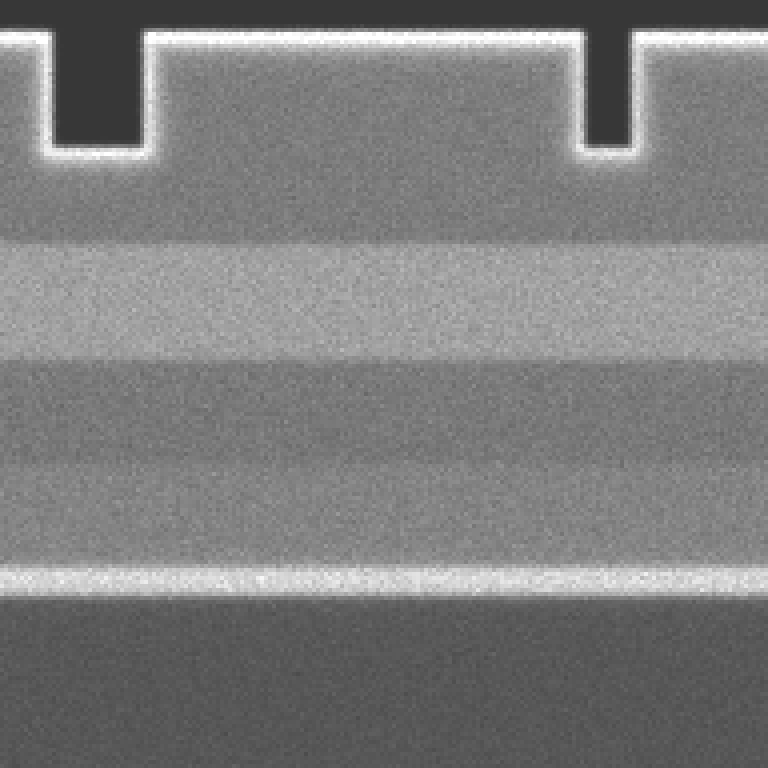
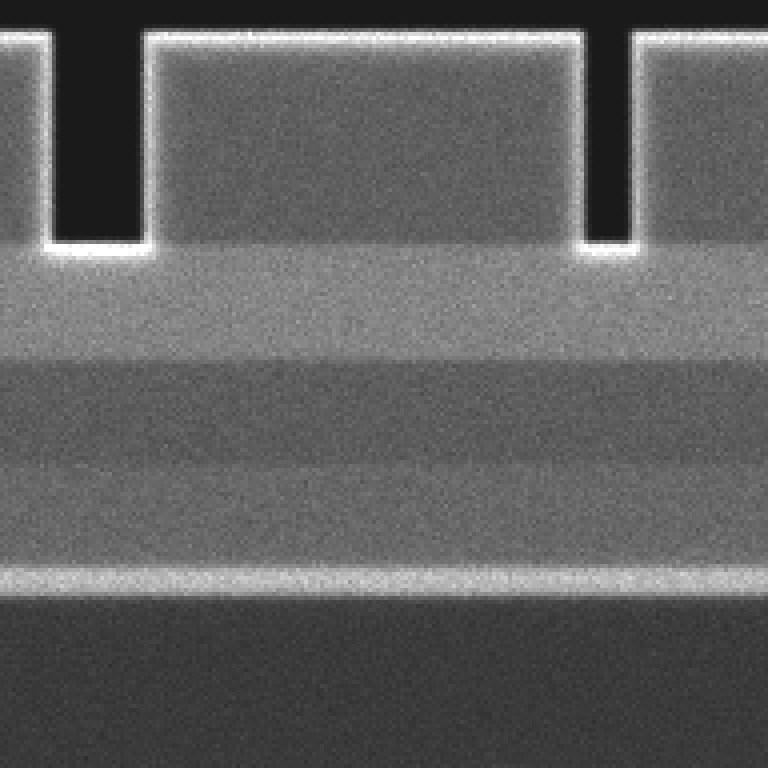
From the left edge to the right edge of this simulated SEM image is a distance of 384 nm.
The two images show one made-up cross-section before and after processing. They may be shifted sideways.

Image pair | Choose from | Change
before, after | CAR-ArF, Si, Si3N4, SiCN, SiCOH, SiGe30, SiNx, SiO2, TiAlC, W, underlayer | underlayer (removed)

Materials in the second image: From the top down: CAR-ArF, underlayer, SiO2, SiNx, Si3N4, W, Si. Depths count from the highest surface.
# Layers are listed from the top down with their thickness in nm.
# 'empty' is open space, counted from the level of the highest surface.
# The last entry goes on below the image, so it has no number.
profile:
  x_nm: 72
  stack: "CAR-ArF 58, underlayer 48, SiO2 58, SiNx 52, Si3N4 52, W 14, Si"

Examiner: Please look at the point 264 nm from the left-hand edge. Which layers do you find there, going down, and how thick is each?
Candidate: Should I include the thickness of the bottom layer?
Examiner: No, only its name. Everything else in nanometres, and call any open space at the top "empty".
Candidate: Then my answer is CAR-ArF 58, underlayer 48, SiO2 58, SiNx 52, Si3N4 52, W 14, Si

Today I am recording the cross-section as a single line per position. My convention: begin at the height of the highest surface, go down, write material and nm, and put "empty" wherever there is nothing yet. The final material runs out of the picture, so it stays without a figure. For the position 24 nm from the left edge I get CAR-ArF 58, underlayer 48, SiO2 58, SiNx 52, Si3N4 52, W 14, Si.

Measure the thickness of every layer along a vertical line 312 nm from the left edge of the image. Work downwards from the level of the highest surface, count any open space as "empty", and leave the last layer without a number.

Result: empty 106, SiO2 58, SiNx 52, Si3N4 52, W 14, Si